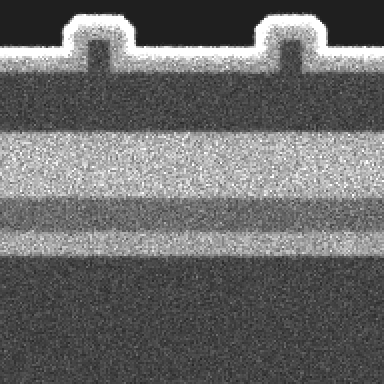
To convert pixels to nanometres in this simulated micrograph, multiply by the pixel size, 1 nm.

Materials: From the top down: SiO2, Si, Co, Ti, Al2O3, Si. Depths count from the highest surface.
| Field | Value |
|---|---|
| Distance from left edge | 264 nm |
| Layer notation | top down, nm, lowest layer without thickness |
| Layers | empty 4, SiO2 52, Si 60, Co 66, Ti 34, Al2O3 24, Si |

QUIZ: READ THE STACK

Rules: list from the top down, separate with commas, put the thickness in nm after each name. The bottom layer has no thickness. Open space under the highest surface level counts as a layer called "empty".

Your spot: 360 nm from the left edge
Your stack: empty 32, SiO2 24, Si 60, Co 66, Ti 34, Al2O3 24, Si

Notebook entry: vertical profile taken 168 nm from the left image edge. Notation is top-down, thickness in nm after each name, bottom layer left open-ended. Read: empty 32, SiO2 24, Si 60, Co 66, Ti 34, Al2O3 24, Si